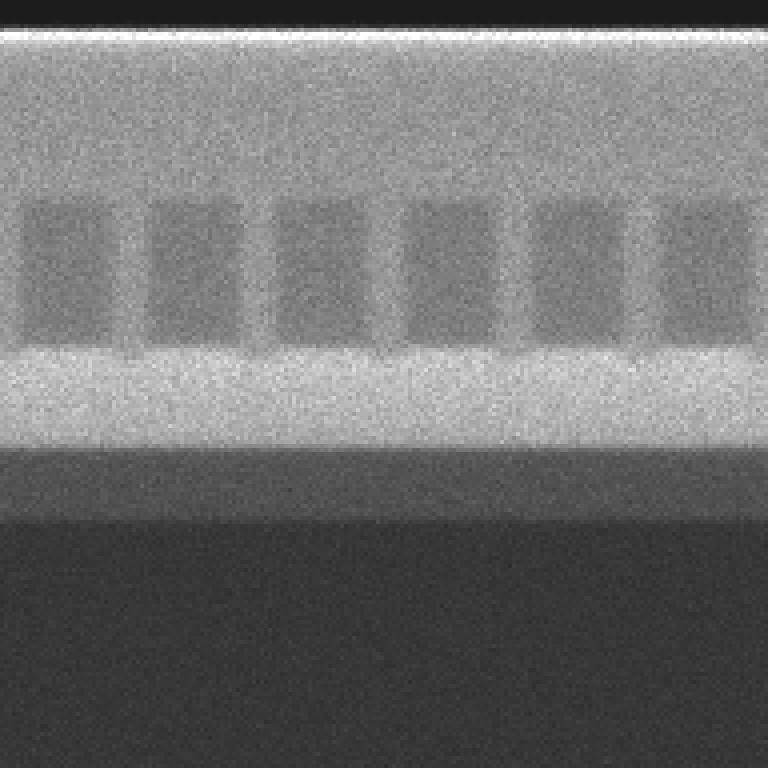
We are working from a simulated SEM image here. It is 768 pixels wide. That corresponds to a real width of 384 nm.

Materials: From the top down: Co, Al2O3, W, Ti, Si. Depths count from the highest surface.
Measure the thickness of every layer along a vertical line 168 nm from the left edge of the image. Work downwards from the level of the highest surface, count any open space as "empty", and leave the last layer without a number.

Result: Co 84, Al2O3 74, W 50, Ti 36, Si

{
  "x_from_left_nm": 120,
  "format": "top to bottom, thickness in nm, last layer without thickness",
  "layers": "Co 164, W 44, Ti 36, Si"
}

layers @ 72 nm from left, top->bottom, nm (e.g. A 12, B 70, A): Co 164, W 44, Ti 36, Si